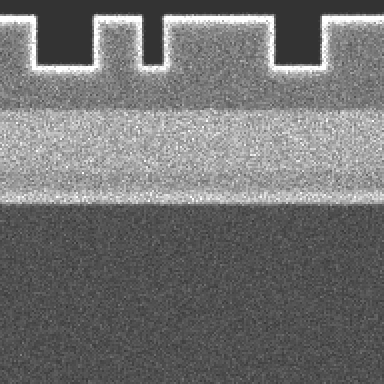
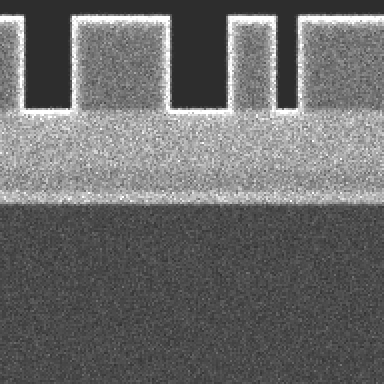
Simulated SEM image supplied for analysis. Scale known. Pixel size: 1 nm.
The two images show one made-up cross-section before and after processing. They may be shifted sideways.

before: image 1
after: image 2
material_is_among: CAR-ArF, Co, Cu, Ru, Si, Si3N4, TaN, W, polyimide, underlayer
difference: underlayer, removed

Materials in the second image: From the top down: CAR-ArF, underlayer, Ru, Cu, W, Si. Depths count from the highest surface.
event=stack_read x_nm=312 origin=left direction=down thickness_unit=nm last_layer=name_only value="CAR-ArF 50, underlayer 44, Ru 62, Cu 20, W 12, Si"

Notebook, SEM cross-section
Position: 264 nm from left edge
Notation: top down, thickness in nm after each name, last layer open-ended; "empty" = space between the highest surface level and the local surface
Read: CAR-ArF 50, underlayer 44, Ru 62, Cu 20, W 12, Si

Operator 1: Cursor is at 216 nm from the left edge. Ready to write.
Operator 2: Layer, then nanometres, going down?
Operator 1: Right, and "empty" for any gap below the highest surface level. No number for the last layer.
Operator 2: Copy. empty 94, Ru 62, Cu 20, W 12, Si